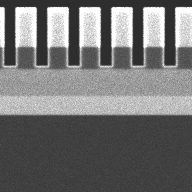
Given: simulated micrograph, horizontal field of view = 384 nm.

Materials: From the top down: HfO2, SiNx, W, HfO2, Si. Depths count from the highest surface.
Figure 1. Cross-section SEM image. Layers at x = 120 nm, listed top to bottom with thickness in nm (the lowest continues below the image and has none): HfO2 78, SiNx 44, W 54, HfO2 38, Si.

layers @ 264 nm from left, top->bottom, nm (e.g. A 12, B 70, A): empty 116, SiNx 6, W 54, HfO2 38, Si